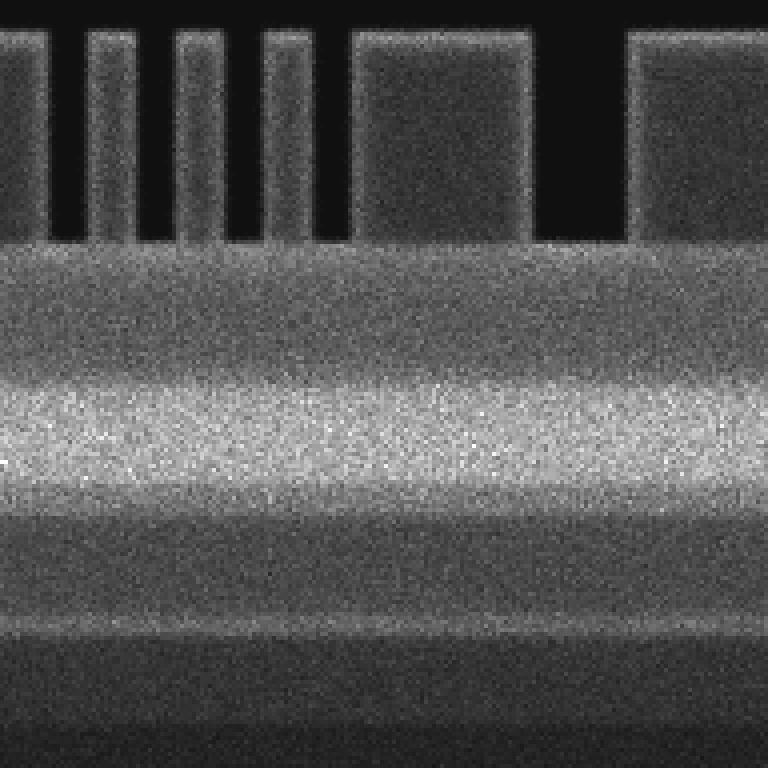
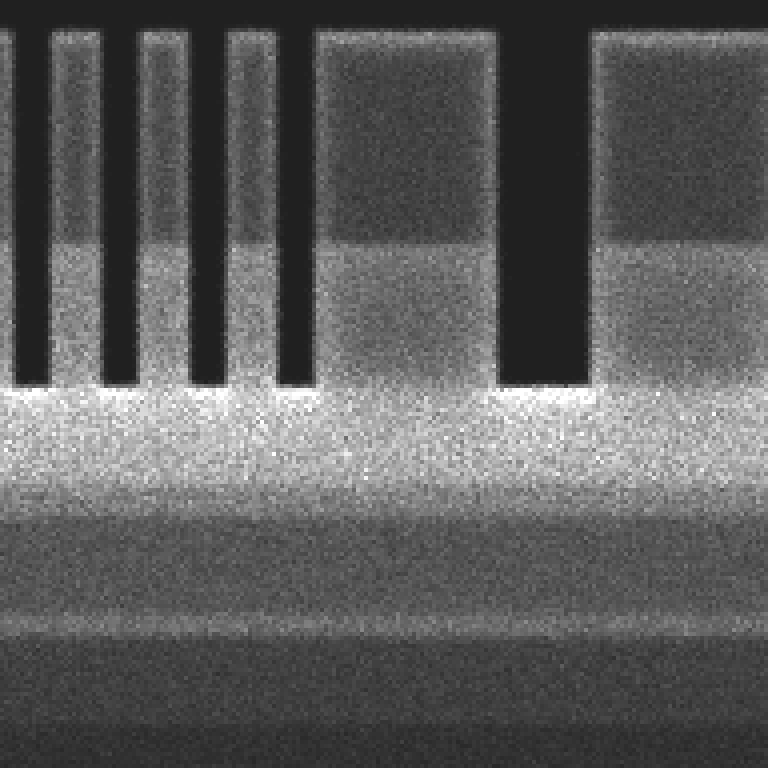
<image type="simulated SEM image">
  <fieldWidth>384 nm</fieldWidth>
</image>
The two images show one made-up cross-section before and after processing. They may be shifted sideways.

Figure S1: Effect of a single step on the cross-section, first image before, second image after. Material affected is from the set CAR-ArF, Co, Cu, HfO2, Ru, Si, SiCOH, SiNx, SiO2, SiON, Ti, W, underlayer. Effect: removed W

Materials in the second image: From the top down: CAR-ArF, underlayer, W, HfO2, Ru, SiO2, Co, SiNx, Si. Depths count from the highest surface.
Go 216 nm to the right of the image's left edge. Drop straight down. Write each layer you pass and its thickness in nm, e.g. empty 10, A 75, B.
CAR-ArF 70, underlayer 36, W 72, HfO2 48, Ru 16, SiO2 50, Co 10, SiNx 44, Si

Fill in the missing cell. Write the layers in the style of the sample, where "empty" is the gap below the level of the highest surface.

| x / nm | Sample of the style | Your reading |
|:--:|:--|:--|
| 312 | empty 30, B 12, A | CAR-ArF 70, underlayer 36, W 72, HfO2 48, Ru 16, SiO2 50, Co 10, SiNx 44, Si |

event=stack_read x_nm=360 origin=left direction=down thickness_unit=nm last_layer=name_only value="CAR-ArF 70, underlayer 36, W 72, HfO2 48, Ru 16, SiO2 50, Co 10, SiNx 44, Si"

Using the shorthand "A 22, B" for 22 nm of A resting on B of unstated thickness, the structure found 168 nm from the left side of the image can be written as CAR-ArF 70, underlayer 36, W 72, HfO2 48, Ru 16, SiO2 50, Co 10, SiNx 44, Si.